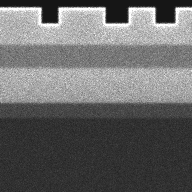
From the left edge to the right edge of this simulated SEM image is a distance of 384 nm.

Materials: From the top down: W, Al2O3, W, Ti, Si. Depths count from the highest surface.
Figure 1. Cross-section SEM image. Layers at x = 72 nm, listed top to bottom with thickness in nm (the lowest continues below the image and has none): W 74, Al2O3 46, W 70, Ti 30, Si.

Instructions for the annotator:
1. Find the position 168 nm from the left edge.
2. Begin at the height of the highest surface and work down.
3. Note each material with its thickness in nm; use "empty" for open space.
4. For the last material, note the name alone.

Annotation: W 74, Al2O3 46, W 70, Ti 30, Si